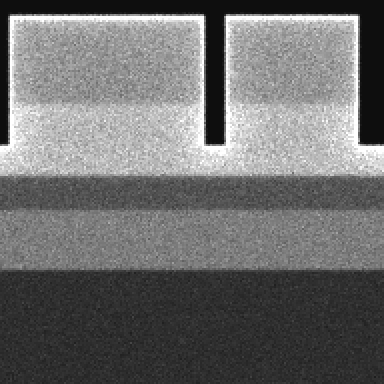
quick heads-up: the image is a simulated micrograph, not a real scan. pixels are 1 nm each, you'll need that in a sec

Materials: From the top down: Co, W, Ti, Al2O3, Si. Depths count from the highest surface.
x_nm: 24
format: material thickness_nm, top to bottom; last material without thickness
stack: Co 88, W 72, Ti 34, Al2O3 60, Si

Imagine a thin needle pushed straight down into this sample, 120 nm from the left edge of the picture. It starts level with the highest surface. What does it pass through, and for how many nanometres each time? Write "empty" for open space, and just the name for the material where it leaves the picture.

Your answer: Co 88, W 72, Ti 34, Al2O3 60, Si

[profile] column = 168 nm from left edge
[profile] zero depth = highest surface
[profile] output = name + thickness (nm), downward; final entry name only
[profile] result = Co 88, W 72, Ti 34, Al2O3 60, Si